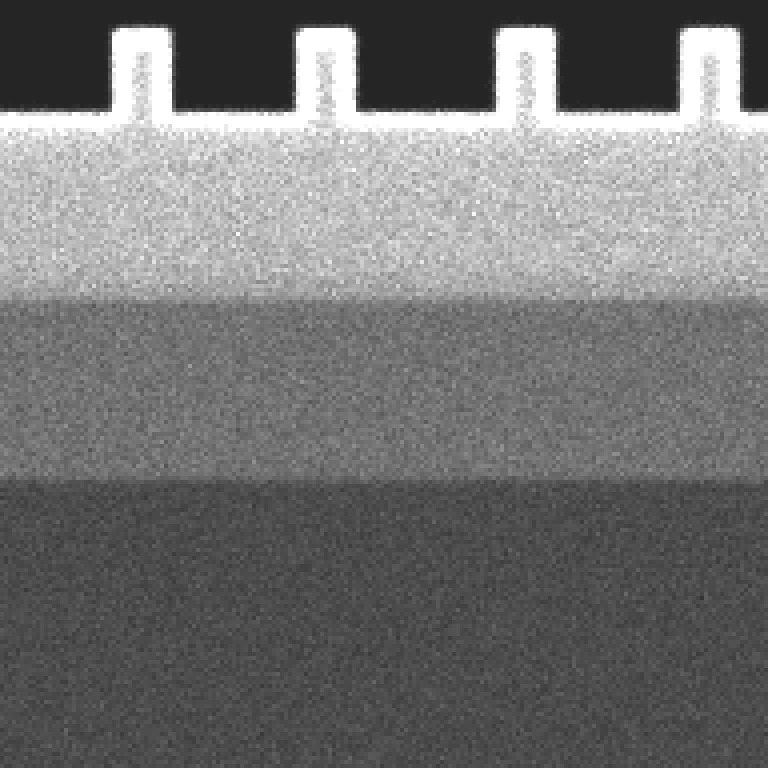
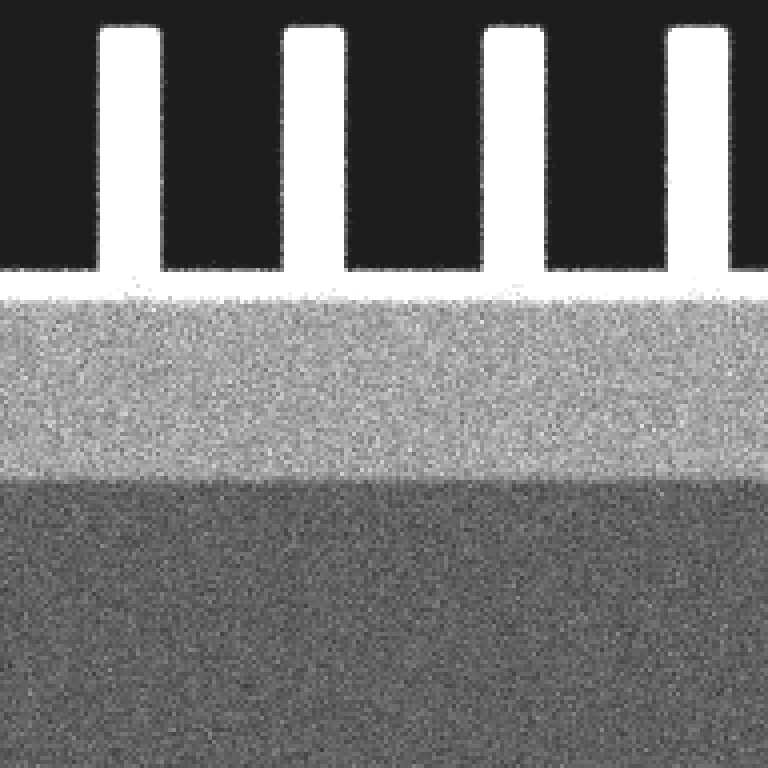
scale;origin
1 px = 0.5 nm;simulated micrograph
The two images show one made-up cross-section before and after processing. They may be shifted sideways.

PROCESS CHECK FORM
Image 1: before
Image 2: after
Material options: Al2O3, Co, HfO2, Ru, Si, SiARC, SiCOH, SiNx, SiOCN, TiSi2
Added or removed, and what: removed, Ru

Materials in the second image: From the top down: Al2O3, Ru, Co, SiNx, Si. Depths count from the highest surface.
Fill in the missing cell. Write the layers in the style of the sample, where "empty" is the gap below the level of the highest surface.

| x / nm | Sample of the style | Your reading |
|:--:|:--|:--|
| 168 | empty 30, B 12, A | Al2O3 42, Ru 80, Co 12, SiNx 90, Si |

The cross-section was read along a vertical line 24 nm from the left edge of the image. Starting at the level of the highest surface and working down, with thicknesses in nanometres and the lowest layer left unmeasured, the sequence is empty 122, Co 12, SiNx 90, Si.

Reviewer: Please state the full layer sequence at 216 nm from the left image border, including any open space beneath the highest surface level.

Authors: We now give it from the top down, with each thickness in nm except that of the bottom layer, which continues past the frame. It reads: empty 122, Co 12, SiNx 90, Si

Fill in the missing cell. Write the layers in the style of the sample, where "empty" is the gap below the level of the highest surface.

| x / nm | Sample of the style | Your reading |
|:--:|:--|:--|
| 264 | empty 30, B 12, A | Al2O3 42, Ru 80, Co 12, SiNx 90, Si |